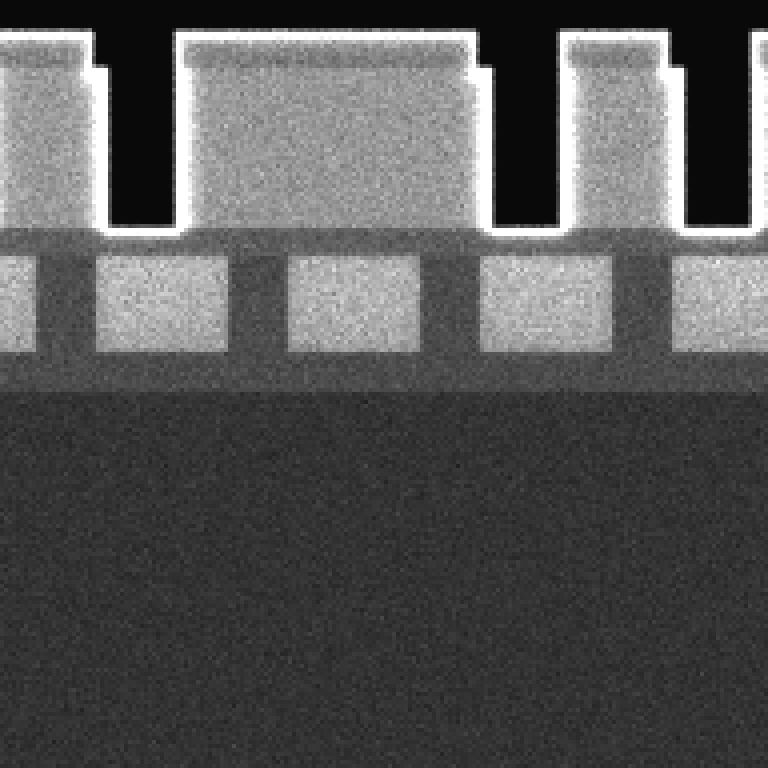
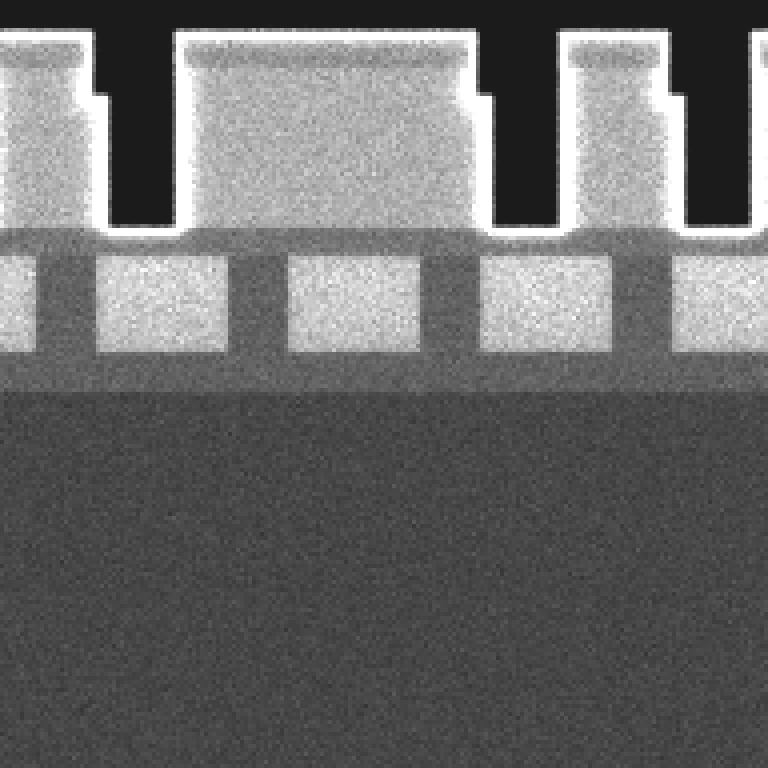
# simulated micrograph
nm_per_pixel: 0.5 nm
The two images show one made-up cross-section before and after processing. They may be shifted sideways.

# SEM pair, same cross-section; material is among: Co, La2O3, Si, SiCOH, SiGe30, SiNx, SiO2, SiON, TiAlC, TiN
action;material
removed;SiO2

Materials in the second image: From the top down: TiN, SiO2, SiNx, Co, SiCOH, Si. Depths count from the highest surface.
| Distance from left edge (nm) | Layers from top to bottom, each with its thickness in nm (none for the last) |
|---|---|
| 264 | empty 98, SiNx 14, Co 48, SiCOH 20, Si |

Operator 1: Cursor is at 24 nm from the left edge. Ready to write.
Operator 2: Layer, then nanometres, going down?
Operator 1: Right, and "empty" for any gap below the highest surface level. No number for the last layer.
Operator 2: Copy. TiN 18, SiO2 80, SiNx 14, SiCOH 68, Si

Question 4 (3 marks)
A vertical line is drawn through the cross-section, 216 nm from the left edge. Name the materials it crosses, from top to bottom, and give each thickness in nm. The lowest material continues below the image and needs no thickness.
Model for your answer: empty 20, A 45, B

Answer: TiN 18, SiO2 80, SiNx 14, SiCOH 68, Si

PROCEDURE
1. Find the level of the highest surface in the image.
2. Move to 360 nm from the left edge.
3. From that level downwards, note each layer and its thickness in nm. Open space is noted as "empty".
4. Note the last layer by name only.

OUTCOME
empty 98, SiNx 14, Co 48, SiCOH 20, Si